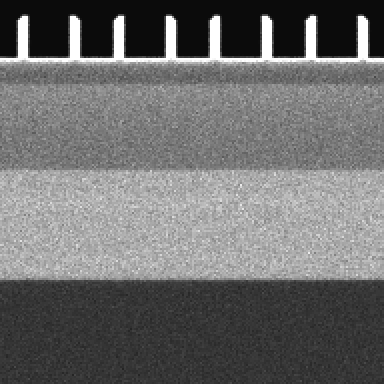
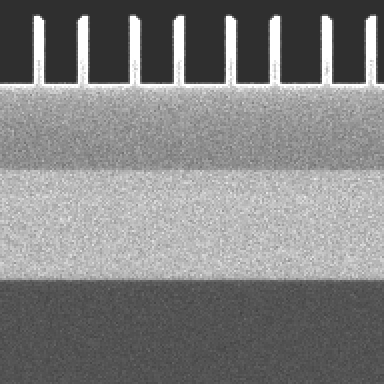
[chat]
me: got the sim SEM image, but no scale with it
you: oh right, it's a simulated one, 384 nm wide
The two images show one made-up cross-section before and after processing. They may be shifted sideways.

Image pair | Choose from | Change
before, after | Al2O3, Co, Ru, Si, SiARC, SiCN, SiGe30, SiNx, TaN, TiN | SiNx (removed)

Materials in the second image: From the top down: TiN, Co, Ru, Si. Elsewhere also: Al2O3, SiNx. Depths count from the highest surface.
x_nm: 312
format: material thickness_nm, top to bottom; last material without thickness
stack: empty 68, TiN 86, Co 24, Ru 86, Si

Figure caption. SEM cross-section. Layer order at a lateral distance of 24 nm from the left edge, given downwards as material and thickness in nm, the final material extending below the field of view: empty 68, TiN 86, Co 24, Ru 86, Si